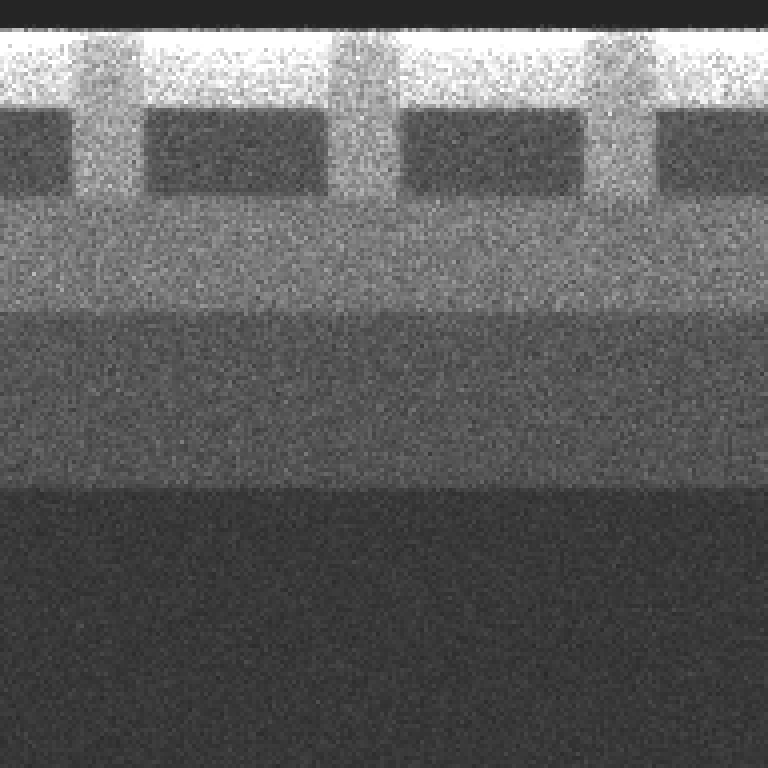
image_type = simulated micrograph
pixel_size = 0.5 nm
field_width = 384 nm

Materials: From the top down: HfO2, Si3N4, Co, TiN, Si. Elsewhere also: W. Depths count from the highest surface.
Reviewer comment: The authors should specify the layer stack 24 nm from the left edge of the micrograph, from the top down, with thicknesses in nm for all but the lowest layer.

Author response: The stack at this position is HfO2 38, Si3N4 44, Co 58, TiN 88, Si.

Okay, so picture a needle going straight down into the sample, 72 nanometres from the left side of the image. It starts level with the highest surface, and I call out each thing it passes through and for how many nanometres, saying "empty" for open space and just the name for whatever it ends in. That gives HfO2 38, Si3N4 44, Co 58, TiN 88, Si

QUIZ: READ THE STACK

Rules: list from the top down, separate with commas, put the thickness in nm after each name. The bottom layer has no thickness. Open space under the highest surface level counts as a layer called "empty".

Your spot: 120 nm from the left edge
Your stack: HfO2 38, Si3N4 44, Co 58, TiN 88, Si